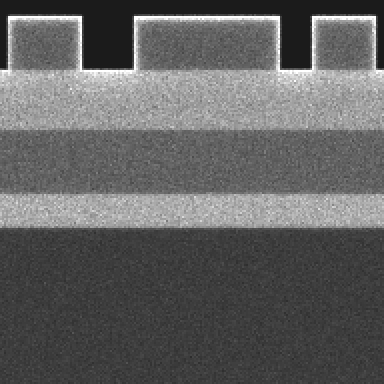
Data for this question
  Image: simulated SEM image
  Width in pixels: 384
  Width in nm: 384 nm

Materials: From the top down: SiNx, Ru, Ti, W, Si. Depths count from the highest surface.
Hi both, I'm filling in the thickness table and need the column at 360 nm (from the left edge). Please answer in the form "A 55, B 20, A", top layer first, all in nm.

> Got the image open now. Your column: SiNx 54, Ru 60, Ti 64, W 34, Si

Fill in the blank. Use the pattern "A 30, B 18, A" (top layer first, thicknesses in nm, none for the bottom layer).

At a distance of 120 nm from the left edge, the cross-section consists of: empty 54, Ru 60, Ti 64, W 34, Si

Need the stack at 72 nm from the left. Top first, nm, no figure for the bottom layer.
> SiNx 54, Ru 60, Ti 64, W 34, Si